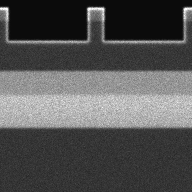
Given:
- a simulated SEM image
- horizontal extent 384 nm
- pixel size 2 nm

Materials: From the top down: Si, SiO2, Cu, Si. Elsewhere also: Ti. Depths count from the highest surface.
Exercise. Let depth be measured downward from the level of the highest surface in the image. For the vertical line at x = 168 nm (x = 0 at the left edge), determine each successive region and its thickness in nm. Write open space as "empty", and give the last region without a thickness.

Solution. empty 66, Si 60, SiO2 48, Cu 66, Si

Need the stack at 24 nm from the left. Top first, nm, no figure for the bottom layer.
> empty 66, Si 60, SiO2 48, Cu 66, Si